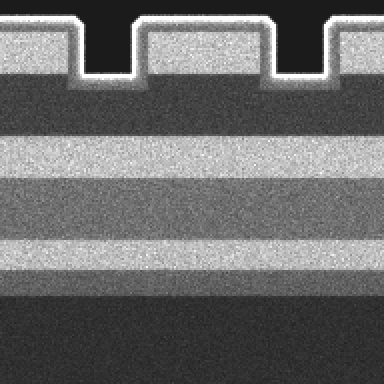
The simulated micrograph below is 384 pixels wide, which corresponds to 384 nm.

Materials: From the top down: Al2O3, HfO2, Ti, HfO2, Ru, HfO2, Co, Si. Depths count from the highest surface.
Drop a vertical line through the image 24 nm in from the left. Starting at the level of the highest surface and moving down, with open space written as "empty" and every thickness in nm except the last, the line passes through Al2O3 16, HfO2 42, Ti 62, HfO2 42, Ru 62, HfO2 30, Co 26, Si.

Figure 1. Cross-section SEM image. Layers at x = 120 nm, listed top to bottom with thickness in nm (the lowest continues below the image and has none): empty 58, Al2O3 16, Ti 46, HfO2 42, Ru 62, HfO2 30, Co 26, Si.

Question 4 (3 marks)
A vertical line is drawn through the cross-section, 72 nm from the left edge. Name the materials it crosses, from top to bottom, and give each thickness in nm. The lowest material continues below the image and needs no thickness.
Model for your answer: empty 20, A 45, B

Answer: Al2O3 74, Ti 46, HfO2 42, Ru 62, HfO2 30, Co 26, Si